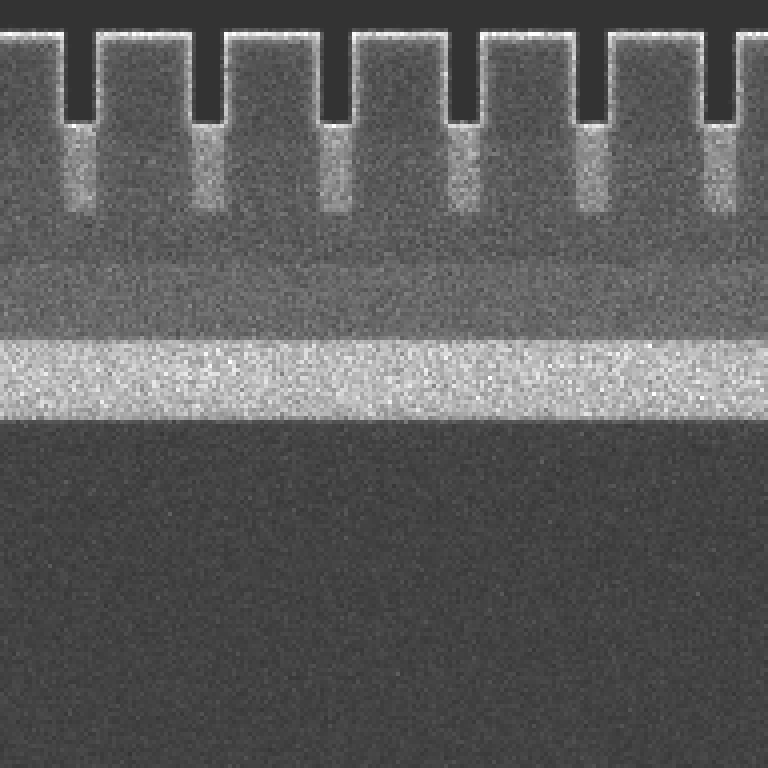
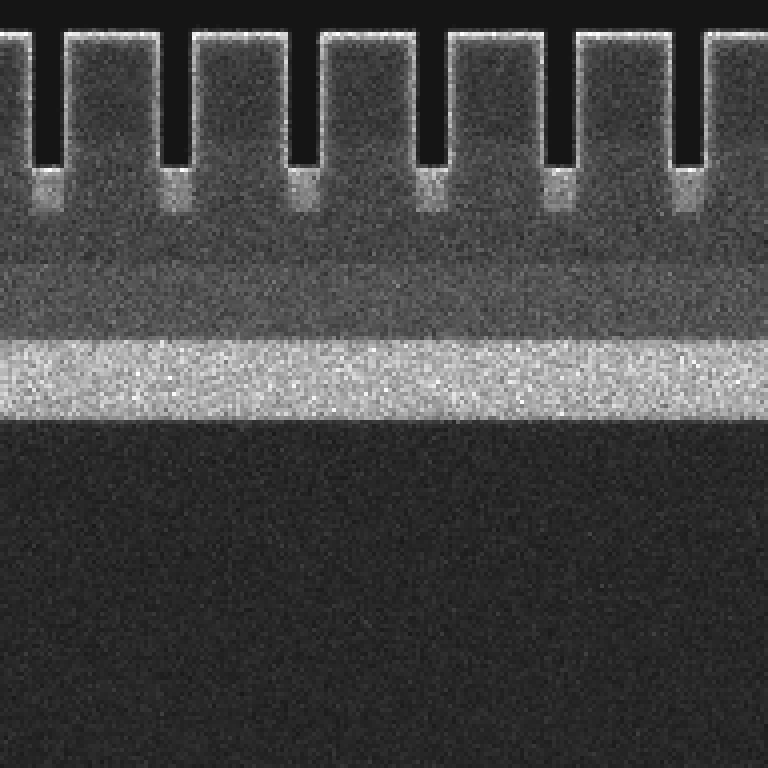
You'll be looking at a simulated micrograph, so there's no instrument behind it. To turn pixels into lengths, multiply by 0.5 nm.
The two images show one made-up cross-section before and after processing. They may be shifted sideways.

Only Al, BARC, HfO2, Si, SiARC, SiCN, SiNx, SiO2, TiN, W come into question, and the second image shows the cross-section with W removed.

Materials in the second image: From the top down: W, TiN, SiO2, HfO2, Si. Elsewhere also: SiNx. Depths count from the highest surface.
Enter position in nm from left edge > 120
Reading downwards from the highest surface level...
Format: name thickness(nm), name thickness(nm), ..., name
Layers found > SiNx 54, TiN 62, SiO2 38, HfO2 40, Si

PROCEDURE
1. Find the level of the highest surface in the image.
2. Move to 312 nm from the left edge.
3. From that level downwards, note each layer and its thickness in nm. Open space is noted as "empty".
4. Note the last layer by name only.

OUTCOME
SiNx 54, TiN 62, SiO2 38, HfO2 40, Si